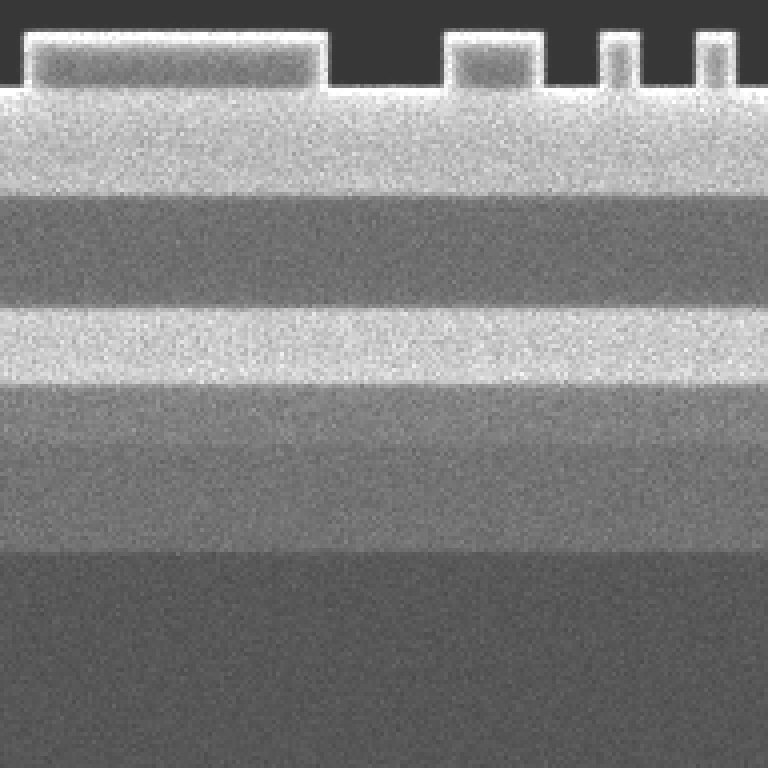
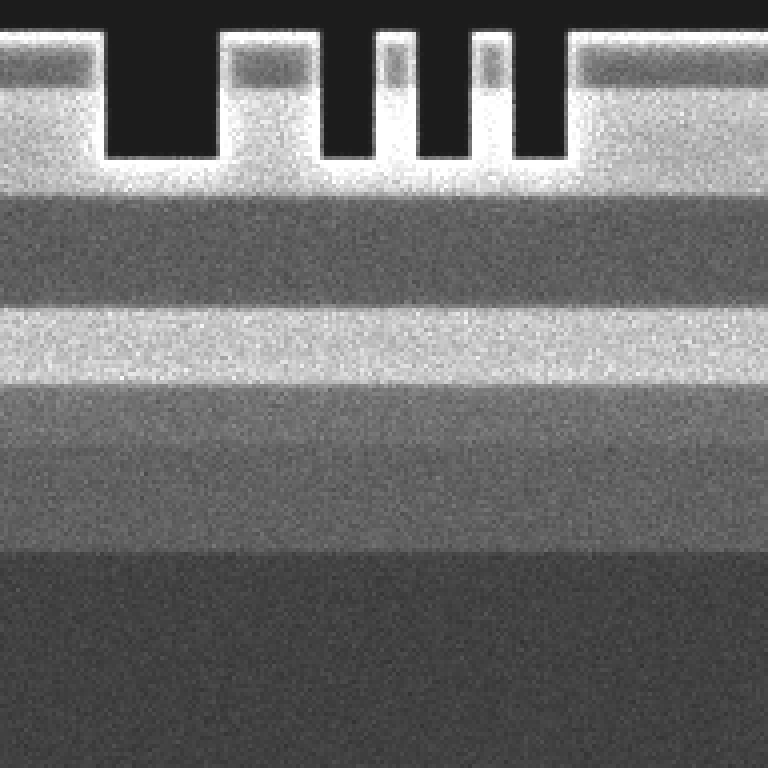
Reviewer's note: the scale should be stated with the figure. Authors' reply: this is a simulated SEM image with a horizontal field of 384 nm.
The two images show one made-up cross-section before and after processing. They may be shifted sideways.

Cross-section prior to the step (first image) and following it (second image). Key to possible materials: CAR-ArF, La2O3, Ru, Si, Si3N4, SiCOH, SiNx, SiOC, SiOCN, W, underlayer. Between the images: Ru was removed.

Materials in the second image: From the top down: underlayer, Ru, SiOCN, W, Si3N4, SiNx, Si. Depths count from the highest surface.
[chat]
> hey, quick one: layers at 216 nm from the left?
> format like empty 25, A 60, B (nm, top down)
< empty 64, Ru 18, SiOCN 56, W 38, Si3N4 30, SiNx 54, Si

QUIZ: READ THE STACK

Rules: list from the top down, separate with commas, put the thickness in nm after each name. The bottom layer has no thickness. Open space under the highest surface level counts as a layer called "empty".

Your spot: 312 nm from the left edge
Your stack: underlayer 28, Ru 54, SiOCN 56, W 38, Si3N4 30, SiNx 54, Si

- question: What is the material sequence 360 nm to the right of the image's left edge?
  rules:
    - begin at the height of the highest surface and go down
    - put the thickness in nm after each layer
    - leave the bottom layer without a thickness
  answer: underlayer 28, Ru 54, SiOCN 56, W 38, Si3N4 30, SiNx 54, Si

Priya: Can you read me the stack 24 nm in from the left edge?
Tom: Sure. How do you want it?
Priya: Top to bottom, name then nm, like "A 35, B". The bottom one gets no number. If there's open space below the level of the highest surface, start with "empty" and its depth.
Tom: underlayer 28, Ru 54, SiOCN 56, W 38, Si3N4 30, SiNx 54, Si